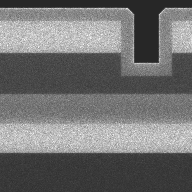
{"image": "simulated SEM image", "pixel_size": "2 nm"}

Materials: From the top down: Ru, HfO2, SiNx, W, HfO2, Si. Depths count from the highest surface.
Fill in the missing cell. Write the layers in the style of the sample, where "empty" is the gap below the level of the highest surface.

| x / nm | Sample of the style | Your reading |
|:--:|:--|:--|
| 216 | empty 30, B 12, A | Ru 26, HfO2 64, SiNx 82, W 60, HfO2 58, Si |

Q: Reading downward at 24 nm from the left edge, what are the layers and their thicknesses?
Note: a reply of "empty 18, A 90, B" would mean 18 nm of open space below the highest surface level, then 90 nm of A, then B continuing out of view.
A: Ru 26, HfO2 64, SiNx 82, W 60, HfO2 58, Si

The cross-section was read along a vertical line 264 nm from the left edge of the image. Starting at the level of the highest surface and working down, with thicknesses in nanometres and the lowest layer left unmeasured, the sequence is empty 10, Ru 126, SiNx 36, W 60, HfO2 58, Si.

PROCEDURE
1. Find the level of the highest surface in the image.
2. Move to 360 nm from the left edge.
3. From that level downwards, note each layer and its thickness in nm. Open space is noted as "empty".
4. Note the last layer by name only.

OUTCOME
Ru 26, HfO2 64, SiNx 82, W 60, HfO2 58, Si